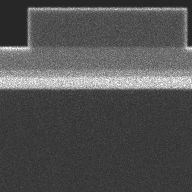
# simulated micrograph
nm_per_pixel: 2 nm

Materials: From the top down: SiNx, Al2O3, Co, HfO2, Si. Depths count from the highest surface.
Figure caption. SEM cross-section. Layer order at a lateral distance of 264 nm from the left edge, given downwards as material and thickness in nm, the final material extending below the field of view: SiNx 78, Al2O3 46, Co 14, HfO2 24, Si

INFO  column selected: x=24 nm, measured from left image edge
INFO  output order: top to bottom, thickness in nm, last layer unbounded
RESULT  empty 78, Al2O3 46, Co 14, HfO2 24, Si